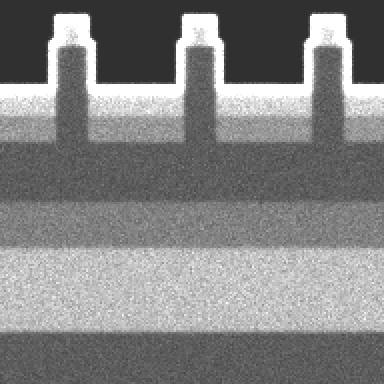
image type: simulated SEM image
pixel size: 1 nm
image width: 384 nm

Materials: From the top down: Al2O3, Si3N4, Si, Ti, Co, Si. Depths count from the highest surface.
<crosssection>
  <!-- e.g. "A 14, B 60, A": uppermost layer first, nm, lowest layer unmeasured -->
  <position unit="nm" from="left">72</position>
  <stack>Al2O3 30, Si 156, Ti 46, Co 84, Si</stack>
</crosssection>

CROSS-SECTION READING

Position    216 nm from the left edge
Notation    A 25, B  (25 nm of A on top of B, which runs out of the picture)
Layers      empty 24, Al2O3 76, Si3N4 26, Si 60, Ti 46, Co 84, Si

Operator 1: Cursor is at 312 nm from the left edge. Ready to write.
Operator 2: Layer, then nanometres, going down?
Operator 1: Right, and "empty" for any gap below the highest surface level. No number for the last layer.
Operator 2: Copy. Al2O3 30, Si 156, Ti 46, Co 84, Si